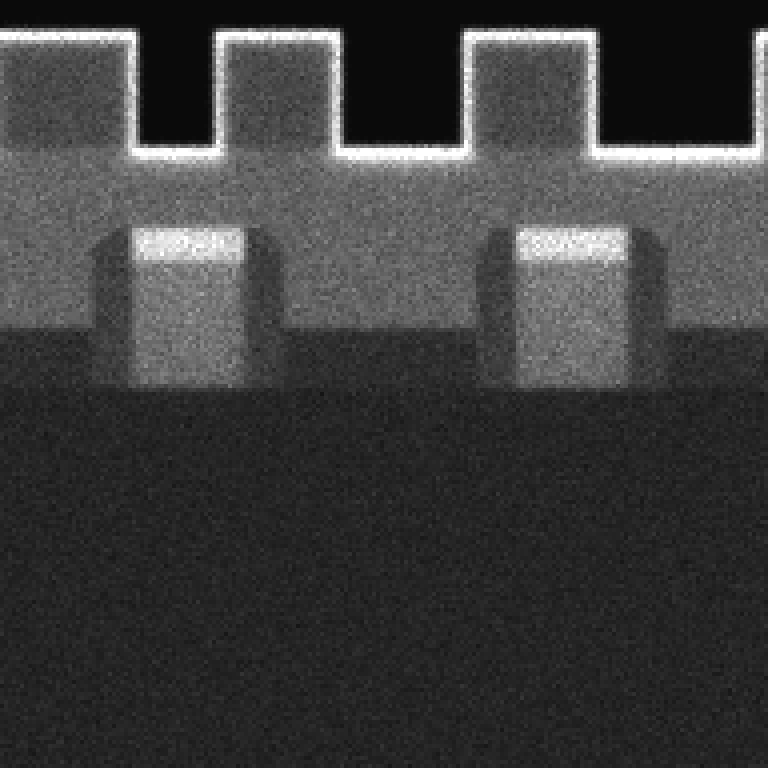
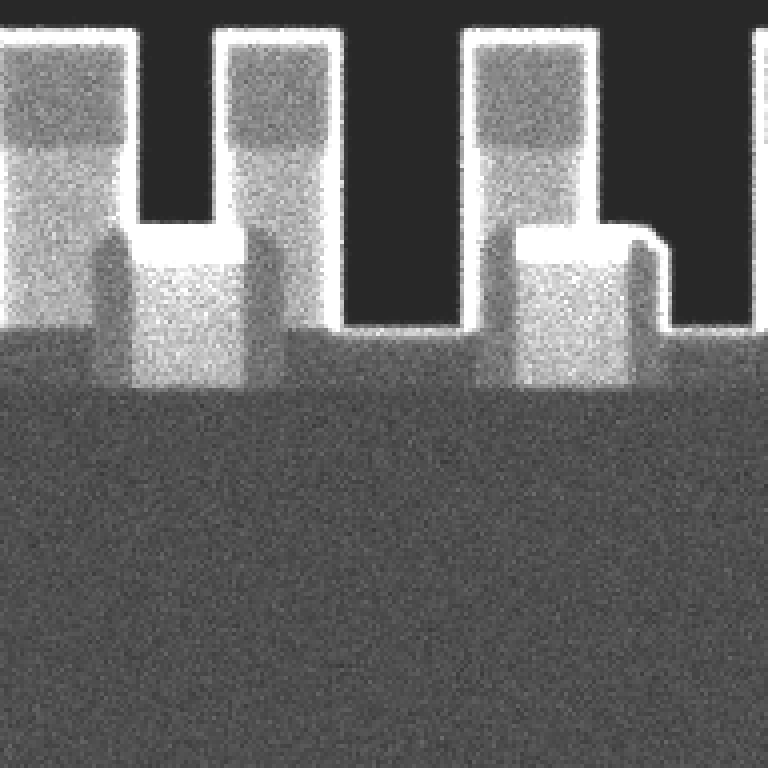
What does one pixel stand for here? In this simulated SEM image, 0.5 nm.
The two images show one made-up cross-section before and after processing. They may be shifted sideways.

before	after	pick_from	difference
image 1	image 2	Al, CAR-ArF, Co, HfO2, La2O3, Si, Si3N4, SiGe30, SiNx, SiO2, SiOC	SiO2 removed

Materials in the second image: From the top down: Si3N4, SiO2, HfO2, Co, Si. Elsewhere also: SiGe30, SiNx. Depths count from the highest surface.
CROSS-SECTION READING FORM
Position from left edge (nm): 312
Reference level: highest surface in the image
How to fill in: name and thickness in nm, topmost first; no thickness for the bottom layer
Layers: empty 98, HfO2 16, Co 64, Si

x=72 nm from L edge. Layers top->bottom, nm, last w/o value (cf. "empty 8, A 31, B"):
empty 98, HfO2 16, Co 64, Si